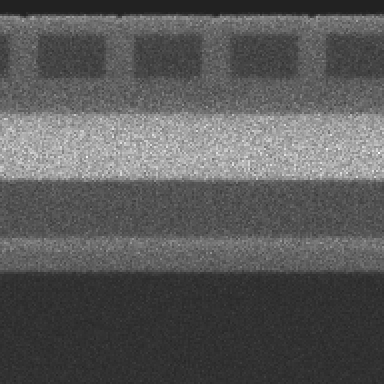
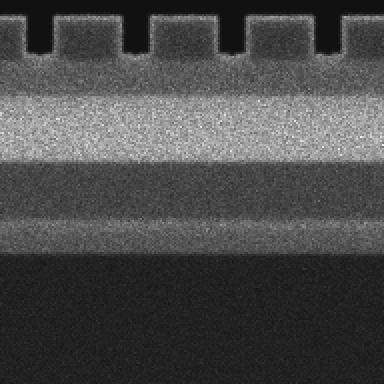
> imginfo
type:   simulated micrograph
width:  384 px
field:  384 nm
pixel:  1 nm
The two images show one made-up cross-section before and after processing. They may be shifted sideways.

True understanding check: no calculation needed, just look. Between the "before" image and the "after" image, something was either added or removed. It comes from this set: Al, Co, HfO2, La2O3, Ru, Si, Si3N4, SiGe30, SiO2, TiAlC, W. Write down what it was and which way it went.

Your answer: Ru (removed)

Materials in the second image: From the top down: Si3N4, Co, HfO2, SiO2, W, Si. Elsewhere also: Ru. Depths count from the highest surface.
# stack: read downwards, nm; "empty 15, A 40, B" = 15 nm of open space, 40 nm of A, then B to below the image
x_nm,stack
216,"Si3N4 44, Co 36, HfO2 66, SiO2 58, W 34, Si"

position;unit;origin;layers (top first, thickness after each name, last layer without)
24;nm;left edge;Si3N4 44, Co 36, HfO2 66, SiO2 58, W 34, Si